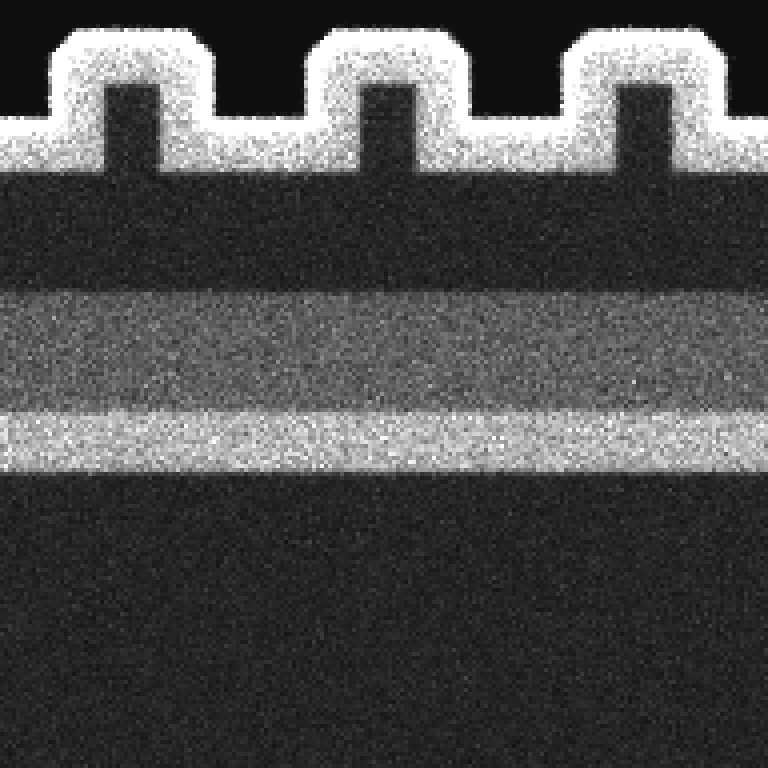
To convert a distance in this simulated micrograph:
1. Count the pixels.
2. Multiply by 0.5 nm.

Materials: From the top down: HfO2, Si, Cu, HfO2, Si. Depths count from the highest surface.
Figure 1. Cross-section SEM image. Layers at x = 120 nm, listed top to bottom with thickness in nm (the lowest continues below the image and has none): empty 44, HfO2 26, Si 60, Cu 60, HfO2 30, Si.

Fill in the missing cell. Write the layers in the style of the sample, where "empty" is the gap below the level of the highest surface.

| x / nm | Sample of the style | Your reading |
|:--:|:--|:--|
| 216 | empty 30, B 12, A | HfO2 70, Si 60, Cu 60, HfO2 30, Si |